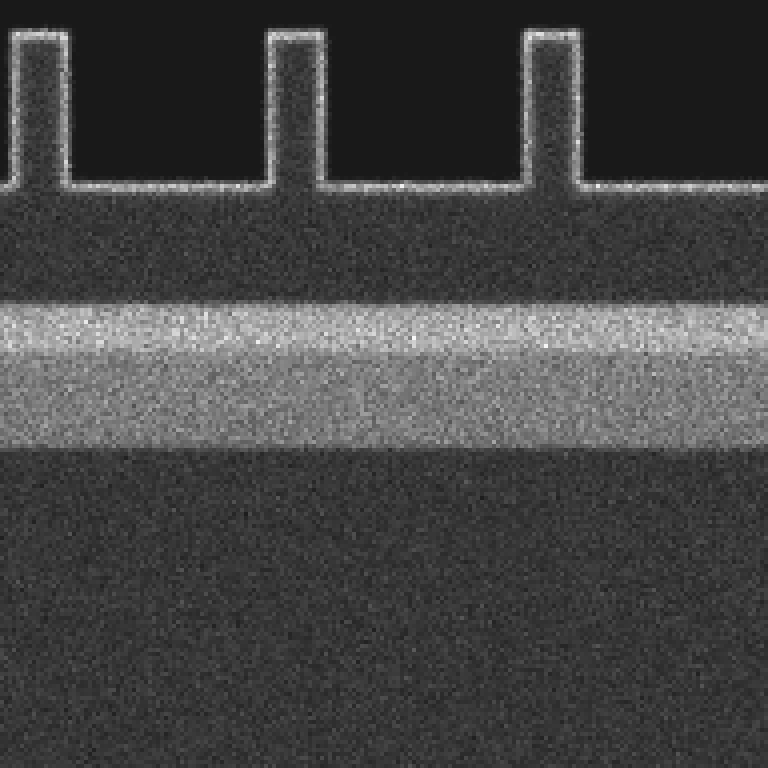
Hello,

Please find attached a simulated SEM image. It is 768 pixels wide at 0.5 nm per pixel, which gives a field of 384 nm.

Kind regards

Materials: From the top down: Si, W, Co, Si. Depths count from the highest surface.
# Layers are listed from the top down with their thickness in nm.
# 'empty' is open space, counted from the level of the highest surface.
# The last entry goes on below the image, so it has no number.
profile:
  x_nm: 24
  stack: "Si 136, W 24, Co 48, Si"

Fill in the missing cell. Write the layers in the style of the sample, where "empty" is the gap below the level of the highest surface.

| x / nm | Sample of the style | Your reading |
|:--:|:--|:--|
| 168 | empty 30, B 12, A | empty 76, Si 60, W 24, Co 48, Si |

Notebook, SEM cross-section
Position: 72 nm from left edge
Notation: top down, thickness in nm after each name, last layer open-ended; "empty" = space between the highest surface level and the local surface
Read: empty 76, Si 60, W 24, Co 48, Si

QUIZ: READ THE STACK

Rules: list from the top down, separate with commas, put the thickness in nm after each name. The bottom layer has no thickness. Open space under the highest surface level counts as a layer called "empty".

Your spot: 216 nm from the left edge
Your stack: empty 76, Si 60, W 24, Co 48, Si